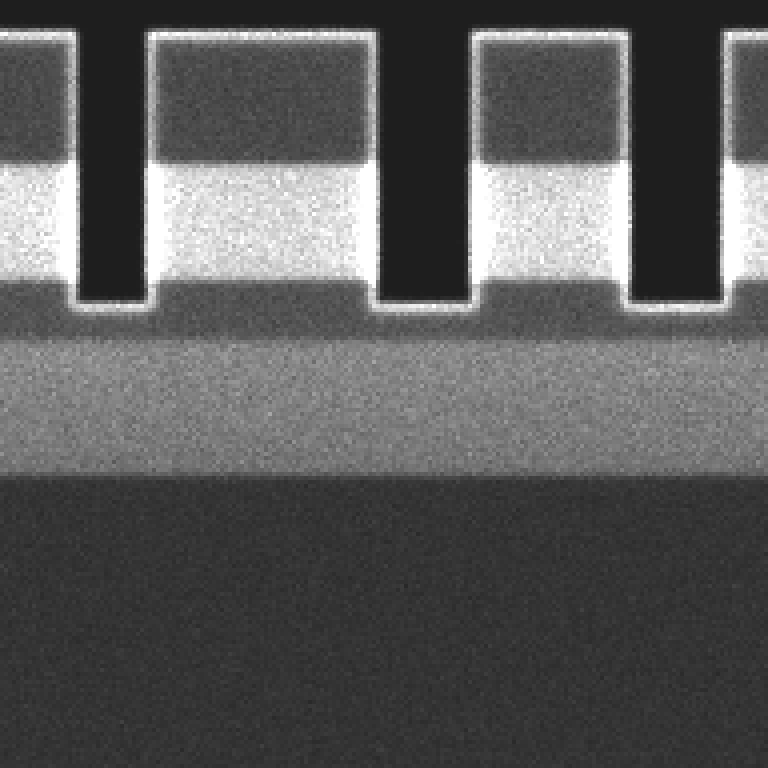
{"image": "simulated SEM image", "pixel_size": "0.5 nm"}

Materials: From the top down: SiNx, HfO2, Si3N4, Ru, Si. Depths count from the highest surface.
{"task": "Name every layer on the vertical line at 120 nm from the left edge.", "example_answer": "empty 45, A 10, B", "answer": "SiNx 66, HfO2 58, Si3N4 30, Ru 68, Si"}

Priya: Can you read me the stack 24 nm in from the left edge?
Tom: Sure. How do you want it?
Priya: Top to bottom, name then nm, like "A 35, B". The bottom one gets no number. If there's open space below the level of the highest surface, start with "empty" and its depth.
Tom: SiNx 66, HfO2 58, Si3N4 30, Ru 68, Si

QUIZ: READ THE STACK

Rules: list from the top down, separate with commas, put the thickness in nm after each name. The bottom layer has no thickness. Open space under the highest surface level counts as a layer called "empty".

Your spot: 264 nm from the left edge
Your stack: SiNx 66, HfO2 58, Si3N4 30, Ru 68, Si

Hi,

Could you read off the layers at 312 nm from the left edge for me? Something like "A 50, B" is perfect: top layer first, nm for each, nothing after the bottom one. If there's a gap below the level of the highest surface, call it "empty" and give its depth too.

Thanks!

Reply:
SiNx 66, HfO2 58, Si3N4 30, Ru 68, Si